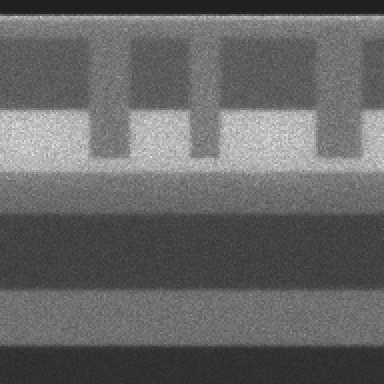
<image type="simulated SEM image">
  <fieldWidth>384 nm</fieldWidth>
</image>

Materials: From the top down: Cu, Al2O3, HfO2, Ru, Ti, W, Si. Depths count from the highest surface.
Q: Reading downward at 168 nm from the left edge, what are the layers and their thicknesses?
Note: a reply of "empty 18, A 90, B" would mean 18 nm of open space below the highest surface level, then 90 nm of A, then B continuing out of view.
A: Cu 22, Al2O3 72, HfO2 62, Ru 42, Ti 76, W 56, Si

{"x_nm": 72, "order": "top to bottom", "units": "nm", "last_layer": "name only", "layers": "Cu 22, Al2O3 72, HfO2 62, Ru 42, Ti 76, W 56, Si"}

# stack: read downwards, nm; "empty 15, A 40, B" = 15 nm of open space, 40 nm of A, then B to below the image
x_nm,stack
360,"Cu 142, HfO2 14, Ru 42, Ti 76, W 56, Si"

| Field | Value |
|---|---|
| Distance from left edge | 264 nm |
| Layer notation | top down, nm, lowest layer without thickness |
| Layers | Cu 22, Al2O3 72, HfO2 62, Ru 42, Ti 76, W 56, Si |